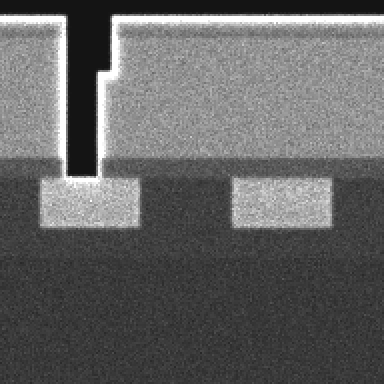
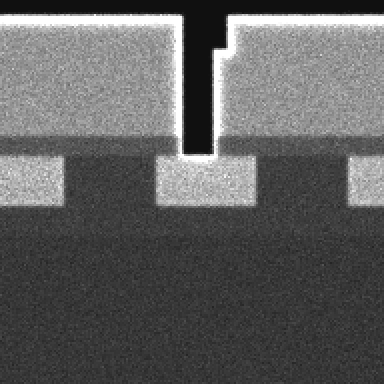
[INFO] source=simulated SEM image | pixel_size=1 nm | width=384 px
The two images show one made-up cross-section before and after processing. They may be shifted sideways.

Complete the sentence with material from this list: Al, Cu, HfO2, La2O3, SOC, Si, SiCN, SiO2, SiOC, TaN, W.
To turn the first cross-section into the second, SOC must be removed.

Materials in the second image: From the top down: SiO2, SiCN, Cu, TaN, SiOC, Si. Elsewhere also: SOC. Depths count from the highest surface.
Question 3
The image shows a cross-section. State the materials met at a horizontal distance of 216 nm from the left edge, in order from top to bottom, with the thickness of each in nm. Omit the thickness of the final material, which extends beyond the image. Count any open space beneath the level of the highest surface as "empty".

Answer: empty 34, SiO2 86, SiCN 20, Cu 44, TaN 6, SiOC 30, Si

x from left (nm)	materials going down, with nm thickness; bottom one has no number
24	SiO2 120, SiCN 20, Cu 44, TaN 6, SiOC 30, Si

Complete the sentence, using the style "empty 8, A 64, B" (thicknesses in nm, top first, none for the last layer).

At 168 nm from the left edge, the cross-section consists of SiO2 120, SiCN 20, Cu 44, TaN 6, SiOC 30, Si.